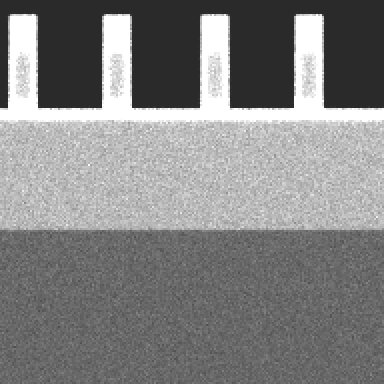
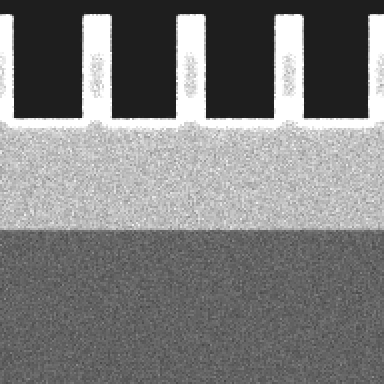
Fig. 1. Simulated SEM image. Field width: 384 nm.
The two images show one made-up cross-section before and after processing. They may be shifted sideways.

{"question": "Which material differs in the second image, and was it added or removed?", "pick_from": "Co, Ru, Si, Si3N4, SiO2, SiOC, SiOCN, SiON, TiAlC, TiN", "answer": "Ru, removed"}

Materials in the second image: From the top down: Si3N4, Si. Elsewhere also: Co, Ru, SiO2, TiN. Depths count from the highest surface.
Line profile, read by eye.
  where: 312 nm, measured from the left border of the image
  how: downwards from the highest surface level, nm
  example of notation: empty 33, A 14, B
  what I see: empty 104, Si3N4 110, Si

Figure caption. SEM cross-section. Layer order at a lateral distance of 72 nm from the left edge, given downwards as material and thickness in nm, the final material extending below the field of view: empty 104, Si3N4 110, Si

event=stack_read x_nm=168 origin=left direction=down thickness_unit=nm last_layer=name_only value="empty 104, Si3N4 110, Si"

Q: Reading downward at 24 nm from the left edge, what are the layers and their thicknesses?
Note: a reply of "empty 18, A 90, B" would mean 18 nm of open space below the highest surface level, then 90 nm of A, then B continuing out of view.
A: empty 104, Si3N4 110, Si